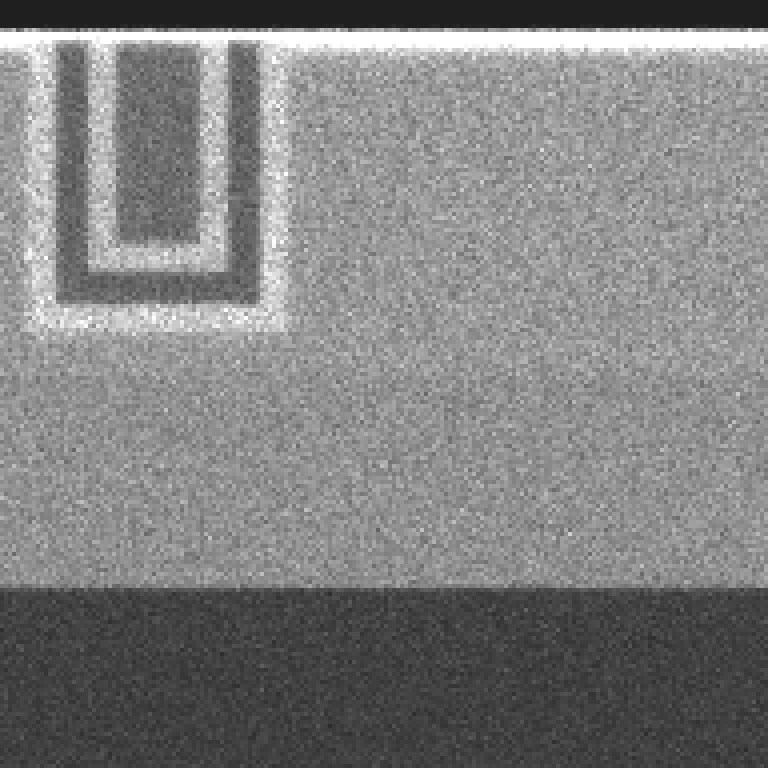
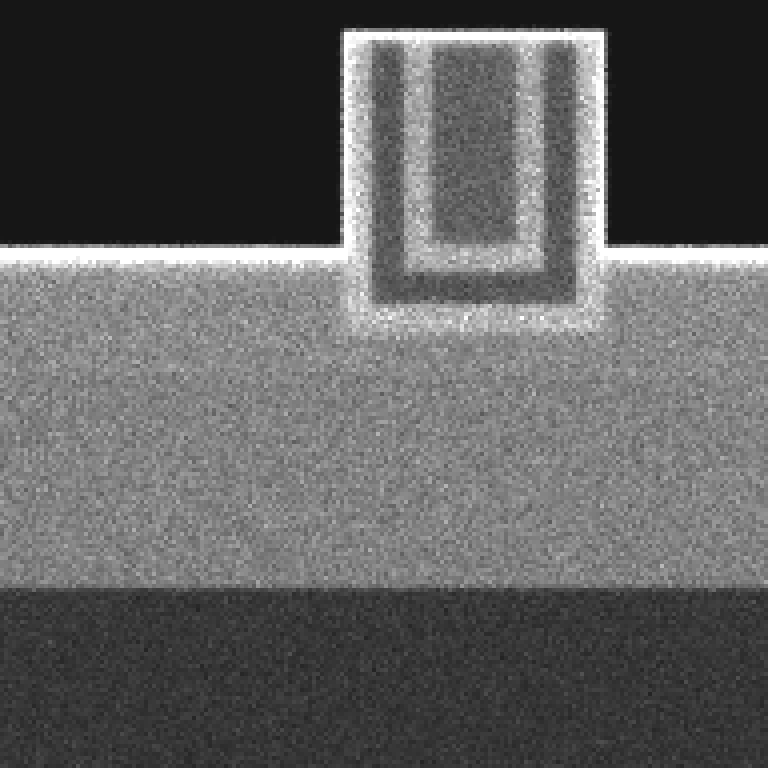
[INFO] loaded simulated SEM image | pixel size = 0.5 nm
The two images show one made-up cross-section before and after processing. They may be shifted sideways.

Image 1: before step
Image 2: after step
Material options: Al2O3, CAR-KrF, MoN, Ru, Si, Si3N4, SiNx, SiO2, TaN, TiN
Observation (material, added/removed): Al2O3, removed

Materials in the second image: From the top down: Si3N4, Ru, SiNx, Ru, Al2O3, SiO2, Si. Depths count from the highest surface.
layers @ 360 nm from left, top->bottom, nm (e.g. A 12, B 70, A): empty 108, Al2O3 64, SiO2 106, Si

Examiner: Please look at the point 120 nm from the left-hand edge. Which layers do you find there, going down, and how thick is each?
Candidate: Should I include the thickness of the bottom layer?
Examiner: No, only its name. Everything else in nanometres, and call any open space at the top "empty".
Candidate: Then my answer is empty 108, Al2O3 64, SiO2 106, Si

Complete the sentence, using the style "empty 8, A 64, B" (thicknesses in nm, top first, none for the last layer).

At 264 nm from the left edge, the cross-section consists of Ru 120, SiNx 16, Ru 14, Al2O3 22, SiO2 106, Si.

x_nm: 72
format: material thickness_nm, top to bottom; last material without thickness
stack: empty 108, Al2O3 64, SiO2 106, Si